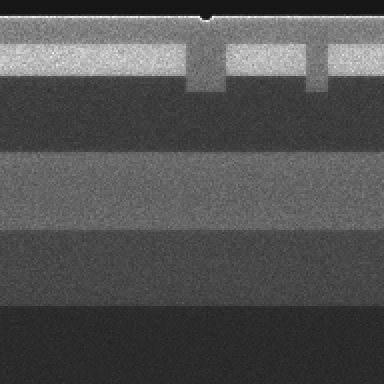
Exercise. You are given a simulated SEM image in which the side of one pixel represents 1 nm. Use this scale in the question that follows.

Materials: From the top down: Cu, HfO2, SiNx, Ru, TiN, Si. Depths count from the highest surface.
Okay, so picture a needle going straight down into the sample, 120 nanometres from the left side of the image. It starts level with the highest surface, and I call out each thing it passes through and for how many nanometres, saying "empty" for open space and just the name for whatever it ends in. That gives Cu 28, HfO2 32, SiNx 76, Ru 78, TiN 76, Si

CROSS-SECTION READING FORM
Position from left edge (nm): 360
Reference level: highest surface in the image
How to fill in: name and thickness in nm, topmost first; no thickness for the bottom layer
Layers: Cu 28, HfO2 32, SiNx 76, Ru 78, TiN 76, Si